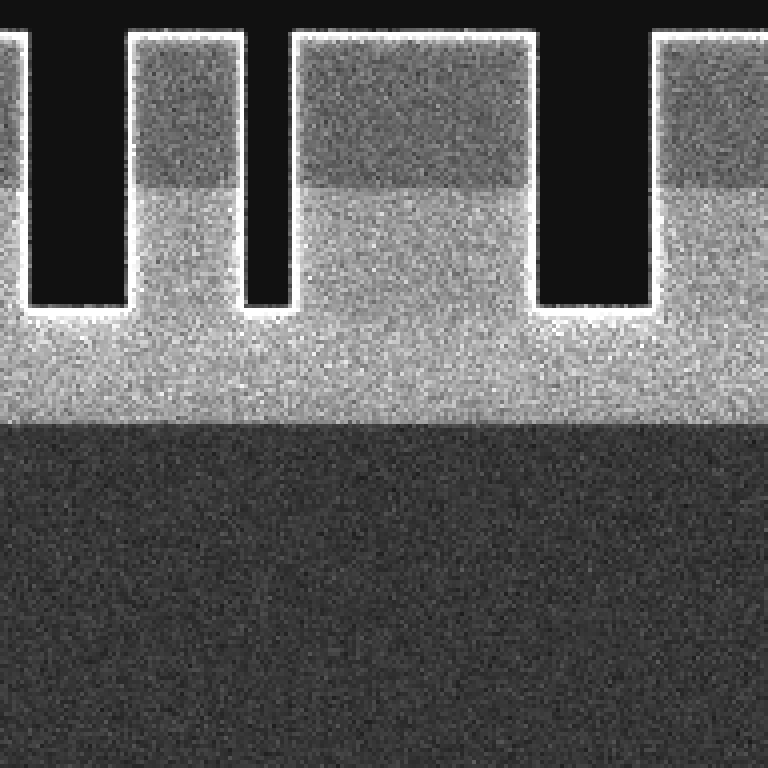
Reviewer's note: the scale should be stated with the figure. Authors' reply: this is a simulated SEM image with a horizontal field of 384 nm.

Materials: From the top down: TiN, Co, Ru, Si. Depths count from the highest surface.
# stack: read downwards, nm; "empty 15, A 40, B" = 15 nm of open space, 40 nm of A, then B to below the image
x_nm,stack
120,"TiN 78, Co 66, Ru 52, Si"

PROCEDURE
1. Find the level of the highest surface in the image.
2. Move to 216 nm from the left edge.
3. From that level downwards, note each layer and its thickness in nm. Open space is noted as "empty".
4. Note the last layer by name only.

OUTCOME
TiN 78, Co 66, Ru 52, Si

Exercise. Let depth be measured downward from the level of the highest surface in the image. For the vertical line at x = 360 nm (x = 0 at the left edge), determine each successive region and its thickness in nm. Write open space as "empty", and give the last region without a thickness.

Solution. TiN 78, Co 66, Ru 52, Si